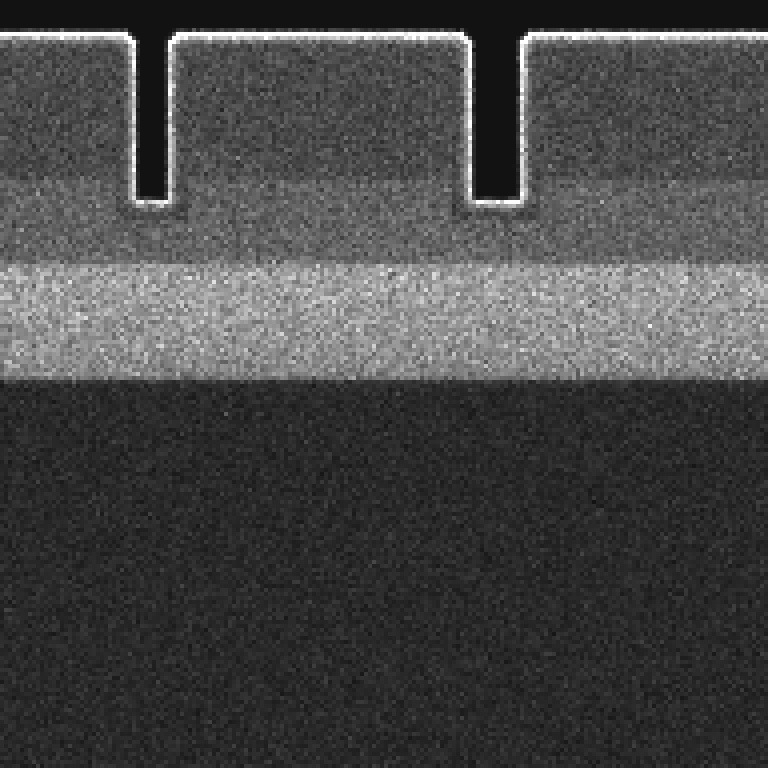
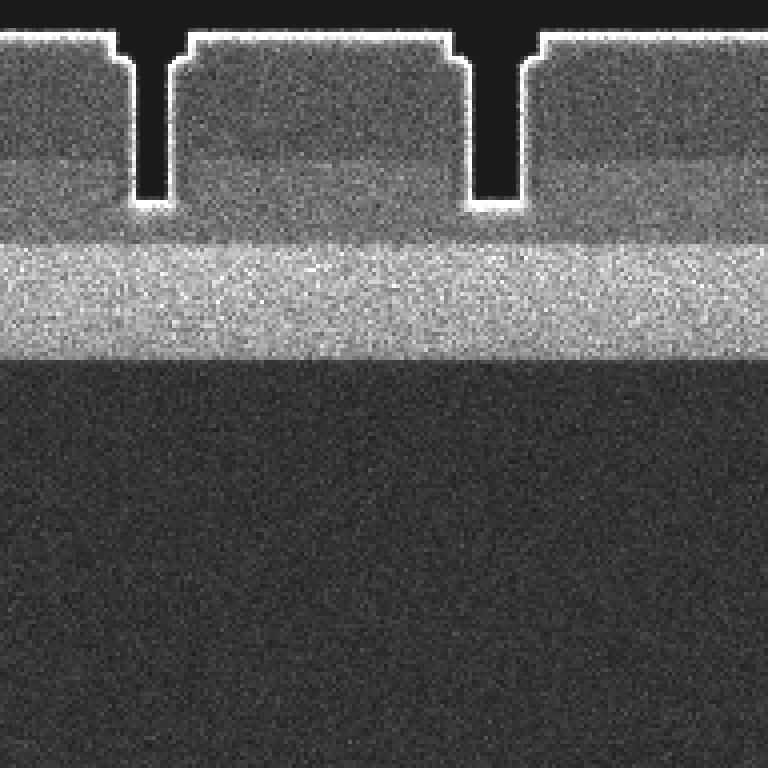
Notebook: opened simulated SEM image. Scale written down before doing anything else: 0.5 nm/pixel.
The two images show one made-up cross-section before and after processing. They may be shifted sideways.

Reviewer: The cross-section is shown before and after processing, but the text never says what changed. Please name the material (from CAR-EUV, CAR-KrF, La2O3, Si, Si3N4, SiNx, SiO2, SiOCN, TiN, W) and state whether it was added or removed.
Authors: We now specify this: SiNx, removed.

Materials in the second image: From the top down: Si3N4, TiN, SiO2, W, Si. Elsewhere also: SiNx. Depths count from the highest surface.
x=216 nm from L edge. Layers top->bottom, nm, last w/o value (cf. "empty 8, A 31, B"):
Si3N4 38, TiN 26, SiO2 42, W 58, Si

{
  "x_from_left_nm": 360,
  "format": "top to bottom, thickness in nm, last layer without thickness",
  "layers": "Si3N4 38, TiN 26, SiO2 42, W 58, Si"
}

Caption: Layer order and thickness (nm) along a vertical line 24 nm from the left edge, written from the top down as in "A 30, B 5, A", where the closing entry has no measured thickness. Si3N4 38, TiN 26, SiO2 42, W 58, Si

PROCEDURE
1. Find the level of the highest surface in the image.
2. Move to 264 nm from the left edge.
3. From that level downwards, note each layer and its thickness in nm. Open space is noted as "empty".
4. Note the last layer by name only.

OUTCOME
empty 12, SiNx 72, SiO2 22, W 58, Si